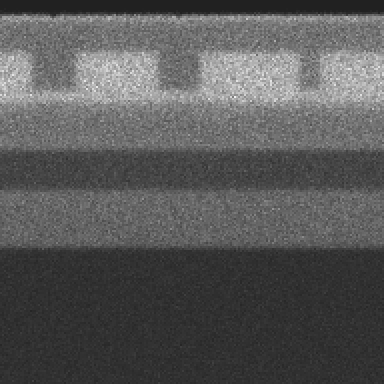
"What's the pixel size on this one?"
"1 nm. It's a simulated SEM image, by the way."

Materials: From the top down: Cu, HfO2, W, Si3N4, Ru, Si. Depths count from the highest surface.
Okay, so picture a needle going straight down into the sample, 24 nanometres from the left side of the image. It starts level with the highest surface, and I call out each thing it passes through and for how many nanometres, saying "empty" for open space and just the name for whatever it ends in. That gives Cu 36, HfO2 50, W 48, Si3N4 40, Ru 58, Si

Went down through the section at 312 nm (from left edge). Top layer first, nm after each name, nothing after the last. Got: Cu 74, HfO2 12, W 48, Si3N4 40, Ru 58, Si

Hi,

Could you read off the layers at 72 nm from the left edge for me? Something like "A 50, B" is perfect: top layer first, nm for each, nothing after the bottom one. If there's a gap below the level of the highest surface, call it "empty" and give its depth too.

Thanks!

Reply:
Cu 74, HfO2 12, W 48, Si3N4 40, Ru 58, Si